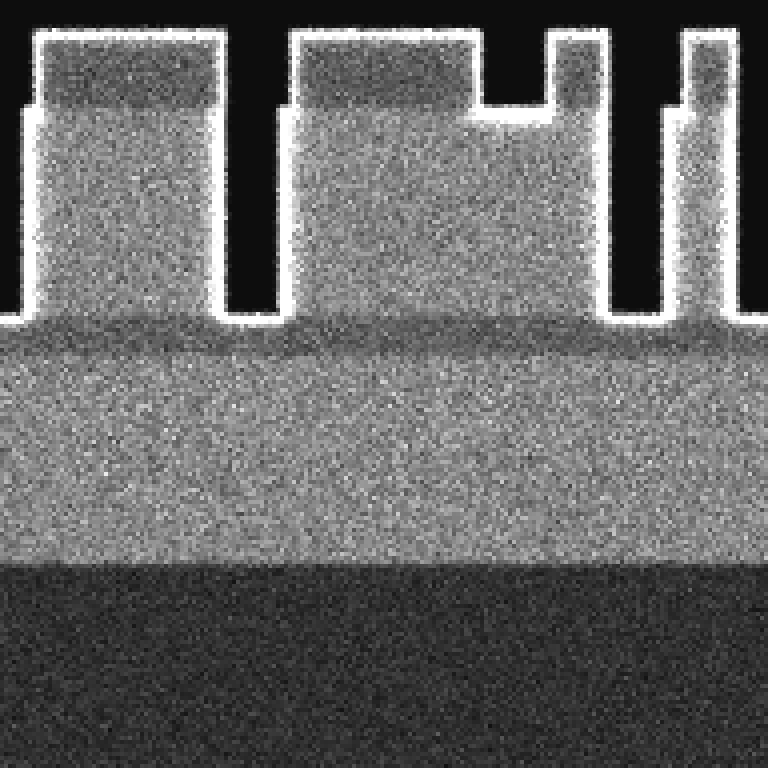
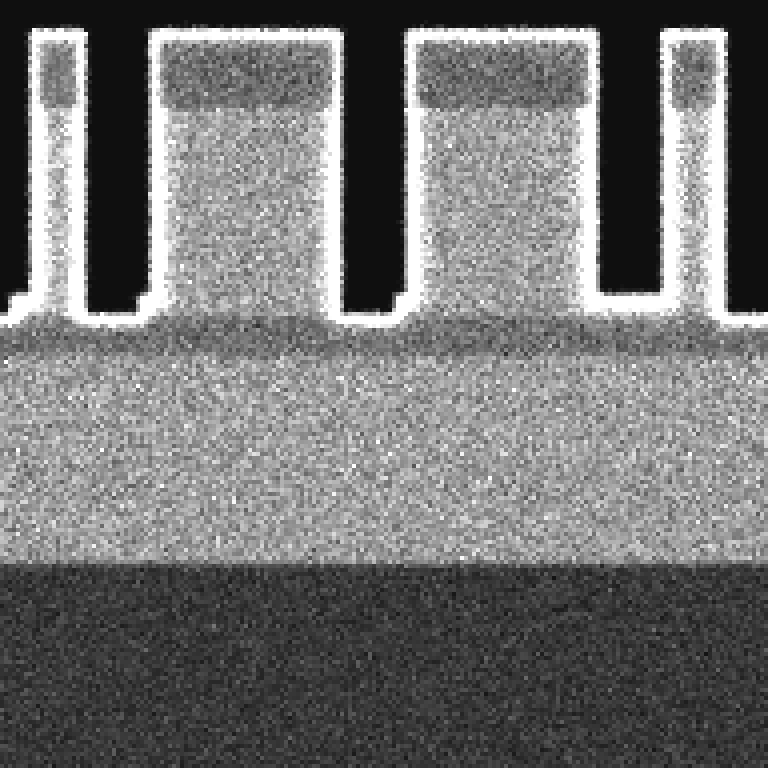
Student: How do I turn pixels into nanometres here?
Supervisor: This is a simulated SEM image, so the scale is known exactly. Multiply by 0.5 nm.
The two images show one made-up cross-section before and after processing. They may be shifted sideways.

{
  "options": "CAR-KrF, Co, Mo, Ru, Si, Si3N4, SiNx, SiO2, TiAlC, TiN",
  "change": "removed",
  "material": "SiO2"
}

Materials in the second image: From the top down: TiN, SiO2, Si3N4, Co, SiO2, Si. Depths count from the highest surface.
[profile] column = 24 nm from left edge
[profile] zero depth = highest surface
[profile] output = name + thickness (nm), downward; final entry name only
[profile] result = TiN 38, SiO2 104, Si3N4 20, SiO2 104, Si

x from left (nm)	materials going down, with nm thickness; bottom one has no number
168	TiN 38, SiO2 104, Si3N4 20, SiO2 104, Si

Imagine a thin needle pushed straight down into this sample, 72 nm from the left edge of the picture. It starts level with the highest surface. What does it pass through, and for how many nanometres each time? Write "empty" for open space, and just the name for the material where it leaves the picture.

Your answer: empty 132, SiO2 10, Si3N4 20, SiO2 104, Si